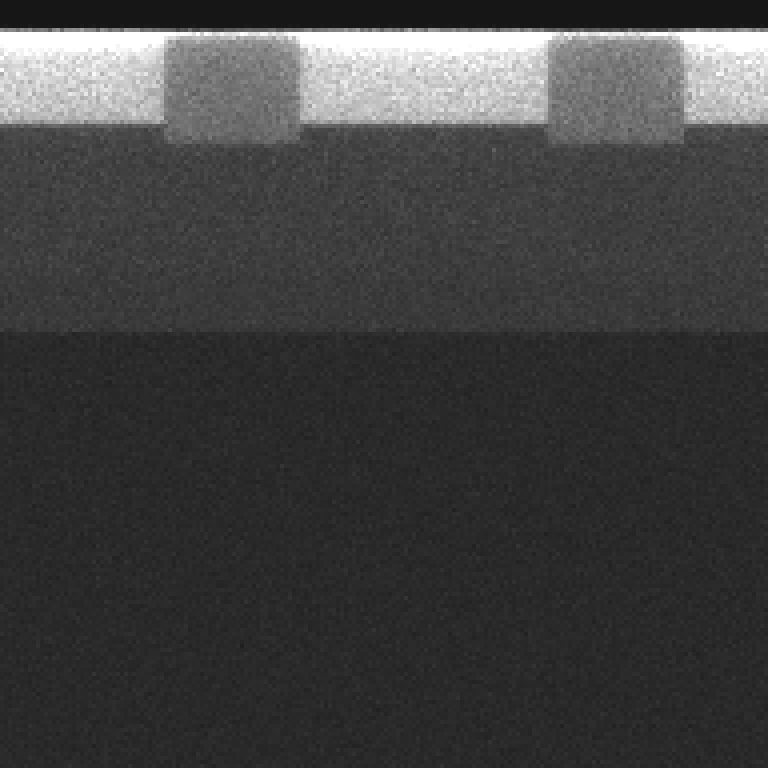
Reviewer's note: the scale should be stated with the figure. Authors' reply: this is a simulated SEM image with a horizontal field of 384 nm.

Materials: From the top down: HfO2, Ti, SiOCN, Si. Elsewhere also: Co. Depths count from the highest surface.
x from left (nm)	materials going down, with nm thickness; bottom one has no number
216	HfO2 46, Ti 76, SiOCN 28, Si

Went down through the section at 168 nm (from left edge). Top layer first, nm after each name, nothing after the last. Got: HfO2 46, Ti 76, SiOCN 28, Si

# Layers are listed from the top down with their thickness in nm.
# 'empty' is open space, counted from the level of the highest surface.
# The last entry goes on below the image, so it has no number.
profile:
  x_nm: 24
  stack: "HfO2 46, Ti 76, SiOCN 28, Si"